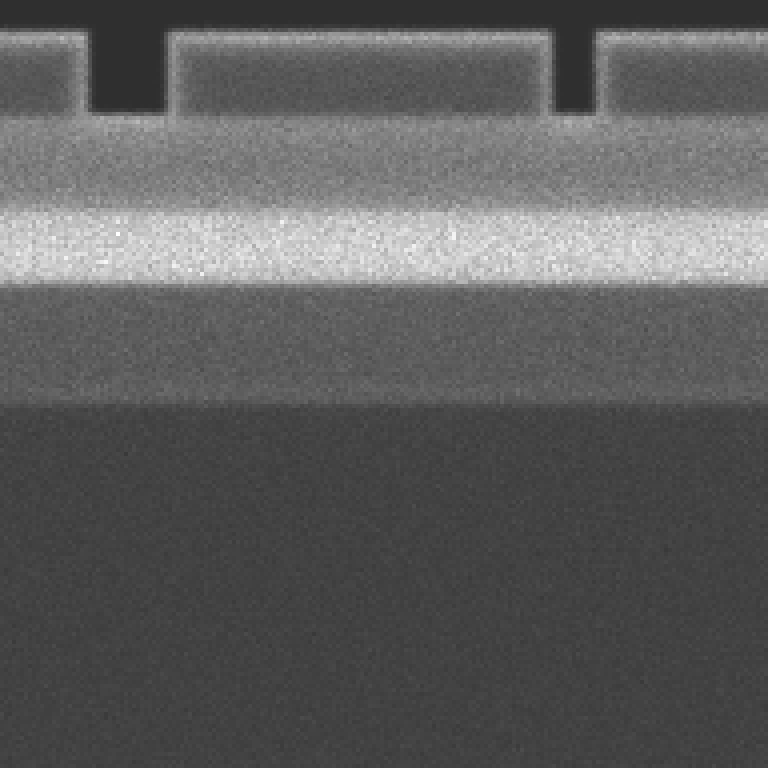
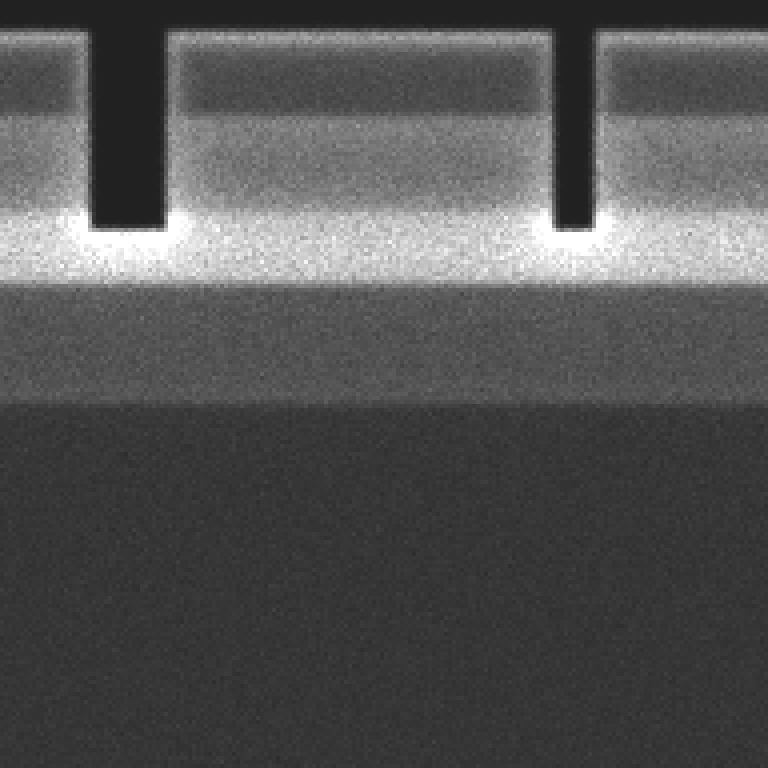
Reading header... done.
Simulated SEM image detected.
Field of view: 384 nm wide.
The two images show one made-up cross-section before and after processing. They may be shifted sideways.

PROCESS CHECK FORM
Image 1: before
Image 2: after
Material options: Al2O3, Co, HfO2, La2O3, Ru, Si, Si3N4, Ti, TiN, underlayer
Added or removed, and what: removed, HfO2 and Ru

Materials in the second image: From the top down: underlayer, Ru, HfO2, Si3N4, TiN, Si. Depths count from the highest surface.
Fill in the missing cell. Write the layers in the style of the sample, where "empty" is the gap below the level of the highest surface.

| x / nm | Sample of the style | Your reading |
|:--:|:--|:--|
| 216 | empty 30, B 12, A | underlayer 42, Ru 48, HfO2 36, Si3N4 50, TiN 10, Si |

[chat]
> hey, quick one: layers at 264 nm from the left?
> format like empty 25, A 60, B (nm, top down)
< underlayer 42, Ru 48, HfO2 36, Si3N4 50, TiN 10, Si